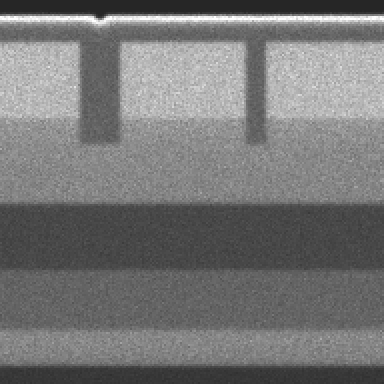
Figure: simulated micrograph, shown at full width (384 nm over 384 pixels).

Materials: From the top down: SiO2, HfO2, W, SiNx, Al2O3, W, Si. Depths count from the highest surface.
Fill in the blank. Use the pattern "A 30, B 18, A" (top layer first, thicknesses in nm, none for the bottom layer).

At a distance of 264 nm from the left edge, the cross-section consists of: SiO2 128, W 60, SiNx 66, Al2O3 60, W 36, Si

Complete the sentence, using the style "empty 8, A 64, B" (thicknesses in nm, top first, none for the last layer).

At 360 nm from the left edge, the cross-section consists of SiO2 26, HfO2 76, W 86, SiNx 66, Al2O3 60, W 36, Si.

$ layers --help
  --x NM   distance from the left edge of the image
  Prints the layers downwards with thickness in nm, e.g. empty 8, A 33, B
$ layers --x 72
SiO2 26, HfO2 76, W 86, SiNx 66, Al2O3 60, W 36, Si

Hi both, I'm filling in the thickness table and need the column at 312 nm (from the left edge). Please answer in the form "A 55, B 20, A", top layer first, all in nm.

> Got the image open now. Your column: SiO2 26, HfO2 76, W 86, SiNx 66, Al2O3 60, W 36, Si